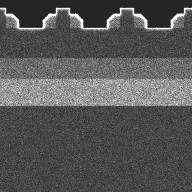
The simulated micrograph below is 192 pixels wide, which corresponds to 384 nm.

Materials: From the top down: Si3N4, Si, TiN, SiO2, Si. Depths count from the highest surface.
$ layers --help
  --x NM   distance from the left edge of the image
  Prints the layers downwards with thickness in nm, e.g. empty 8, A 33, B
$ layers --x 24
empty 12, Si3N4 28, Si 60, TiN 42, SiO2 54, Si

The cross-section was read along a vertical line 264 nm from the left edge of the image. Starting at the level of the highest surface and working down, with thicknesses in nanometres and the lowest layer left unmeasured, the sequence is Si 100, TiN 42, SiO2 54, Si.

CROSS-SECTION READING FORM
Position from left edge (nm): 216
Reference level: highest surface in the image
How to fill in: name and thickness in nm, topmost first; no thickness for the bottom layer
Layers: empty 22, Si3N4 18, Si 60, TiN 42, SiO2 54, Si